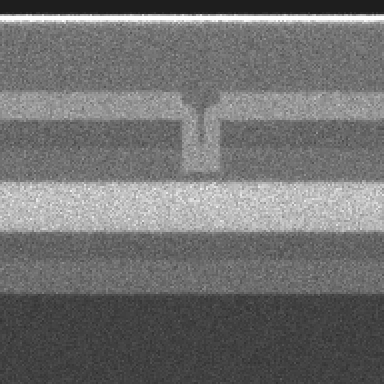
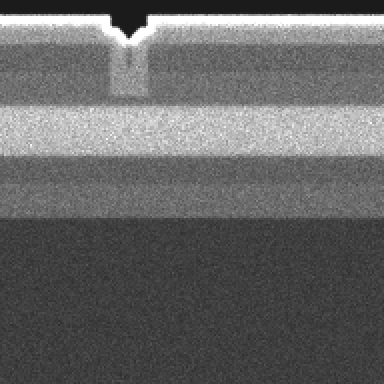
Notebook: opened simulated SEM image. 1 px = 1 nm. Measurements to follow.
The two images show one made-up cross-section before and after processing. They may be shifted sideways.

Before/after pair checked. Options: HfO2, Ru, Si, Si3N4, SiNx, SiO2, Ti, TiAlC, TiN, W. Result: removed Si3N4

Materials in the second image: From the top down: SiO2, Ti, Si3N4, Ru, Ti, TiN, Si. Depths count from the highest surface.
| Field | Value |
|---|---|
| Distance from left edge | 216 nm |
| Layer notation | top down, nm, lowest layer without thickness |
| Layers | SiO2 28, Ti 28, Si3N4 34, Ru 50, Ti 28, TiN 34, Si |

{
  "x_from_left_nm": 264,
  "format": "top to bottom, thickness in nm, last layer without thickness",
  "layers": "SiO2 28, Ti 28, Si3N4 34, Ru 50, Ti 28, TiN 34, Si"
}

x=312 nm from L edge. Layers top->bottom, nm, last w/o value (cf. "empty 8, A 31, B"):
SiO2 28, Ti 28, Si3N4 34, Ru 50, Ti 28, TiN 34, Si